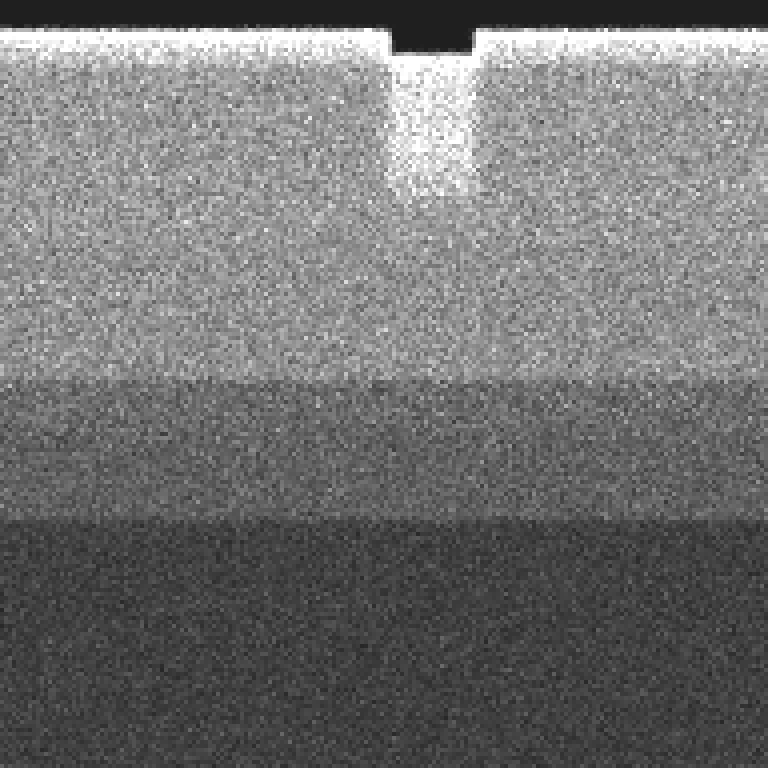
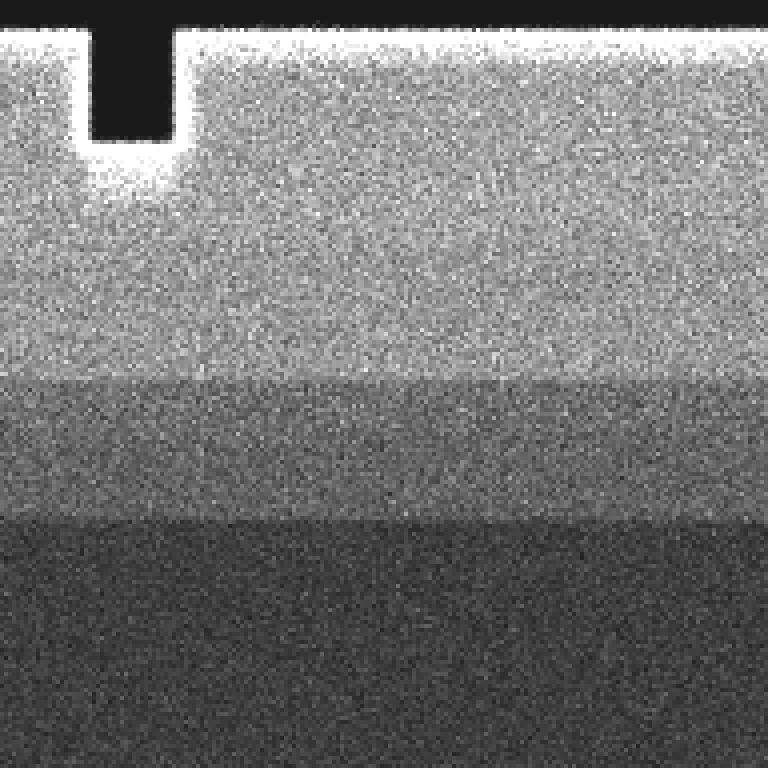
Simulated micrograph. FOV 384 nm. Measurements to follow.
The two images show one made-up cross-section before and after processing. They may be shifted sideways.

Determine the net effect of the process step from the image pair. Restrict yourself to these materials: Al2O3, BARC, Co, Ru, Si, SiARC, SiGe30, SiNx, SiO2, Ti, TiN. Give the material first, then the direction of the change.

Ru: removed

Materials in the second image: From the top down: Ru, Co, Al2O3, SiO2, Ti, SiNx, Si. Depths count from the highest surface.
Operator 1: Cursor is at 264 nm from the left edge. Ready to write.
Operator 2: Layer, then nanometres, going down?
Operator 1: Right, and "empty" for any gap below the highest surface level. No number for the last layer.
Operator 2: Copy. Co 16, Al2O3 90, SiO2 68, Ti 28, SiNx 42, Si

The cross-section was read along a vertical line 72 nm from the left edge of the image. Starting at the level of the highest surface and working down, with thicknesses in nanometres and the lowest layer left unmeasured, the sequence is empty 56, Ru 12, Co 16, Al2O3 22, SiO2 68, Ti 28, SiNx 42, Si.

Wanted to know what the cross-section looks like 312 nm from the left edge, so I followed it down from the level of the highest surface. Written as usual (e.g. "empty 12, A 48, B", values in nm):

Co 16, Al2O3 90, SiO2 68, Ti 28, SiNx 42, Si